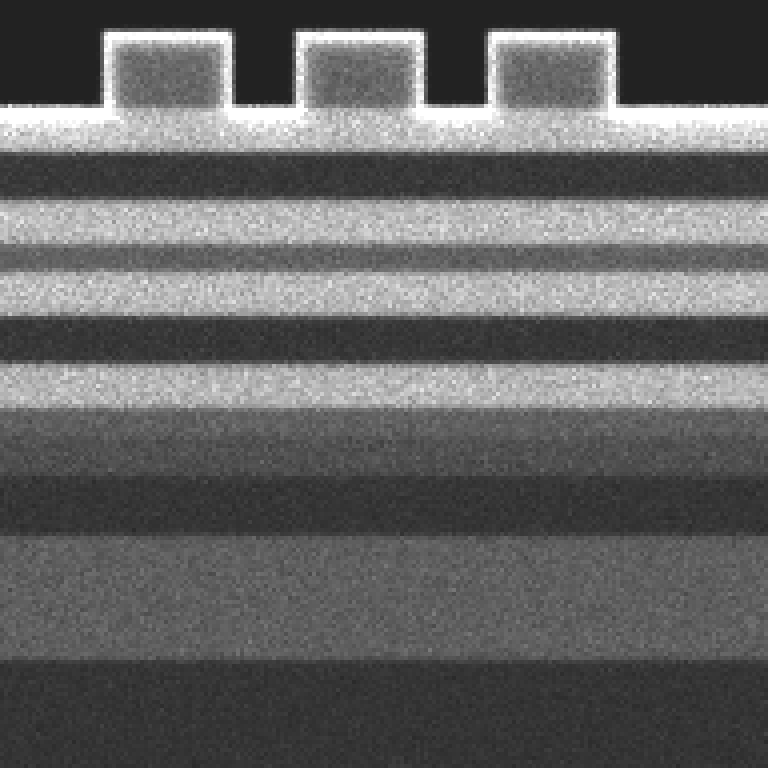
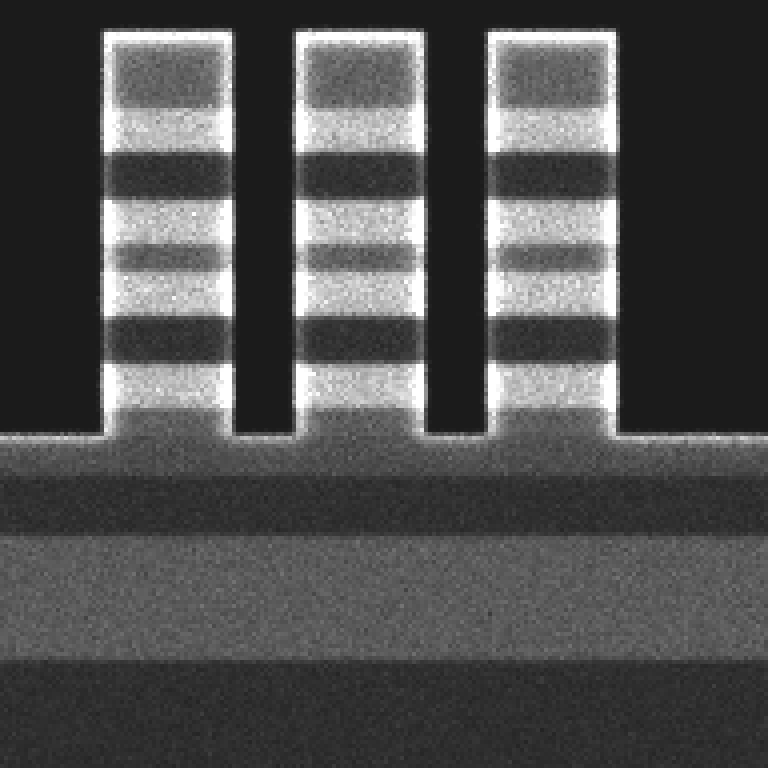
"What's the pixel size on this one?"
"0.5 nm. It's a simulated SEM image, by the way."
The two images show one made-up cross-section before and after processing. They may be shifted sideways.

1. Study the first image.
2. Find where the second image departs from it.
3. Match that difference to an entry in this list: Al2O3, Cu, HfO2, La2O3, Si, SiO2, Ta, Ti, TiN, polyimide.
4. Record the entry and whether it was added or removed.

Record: HfO2 and Si and SiO2 / removed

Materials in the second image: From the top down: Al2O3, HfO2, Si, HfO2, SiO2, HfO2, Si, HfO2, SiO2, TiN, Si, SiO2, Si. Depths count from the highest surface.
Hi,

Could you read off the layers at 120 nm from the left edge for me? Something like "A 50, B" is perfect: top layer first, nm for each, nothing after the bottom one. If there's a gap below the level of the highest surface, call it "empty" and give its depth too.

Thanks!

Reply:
empty 202, TiN 20, Si 30, SiO2 62, Si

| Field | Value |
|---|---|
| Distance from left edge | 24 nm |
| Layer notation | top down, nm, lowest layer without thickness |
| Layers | empty 202, TiN 20, Si 30, SiO2 62, Si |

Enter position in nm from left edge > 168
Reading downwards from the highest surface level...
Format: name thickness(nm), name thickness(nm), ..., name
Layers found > Al2O3 38, HfO2 22, Si 24, HfO2 22, SiO2 14, HfO2 22, Si 24, HfO2 22, SiO2 14, TiN 20, Si 30, SiO2 62, Si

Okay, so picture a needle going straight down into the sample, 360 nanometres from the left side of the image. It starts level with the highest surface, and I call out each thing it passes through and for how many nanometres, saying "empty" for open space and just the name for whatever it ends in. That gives empty 202, TiN 20, Si 30, SiO2 62, Si